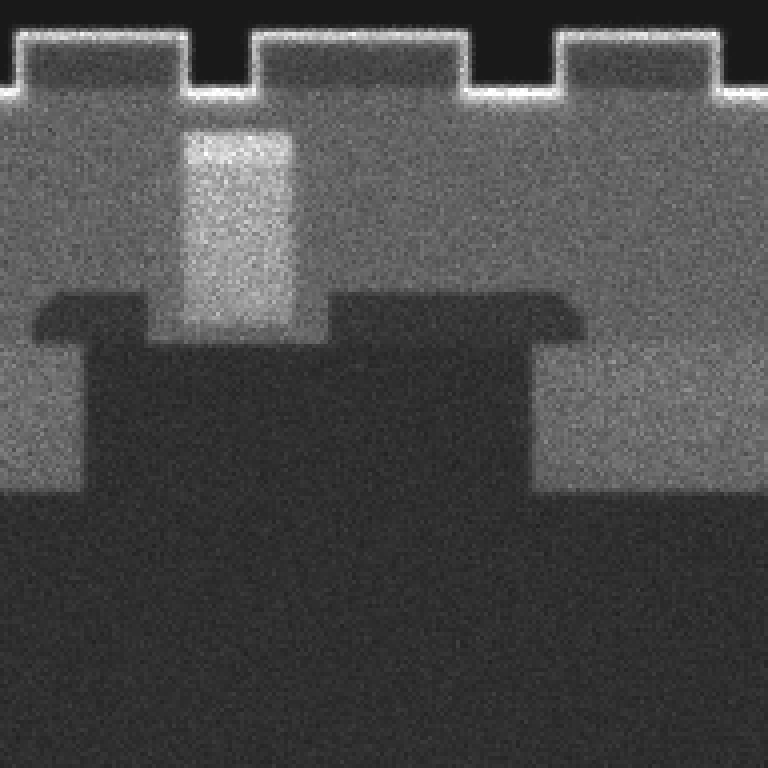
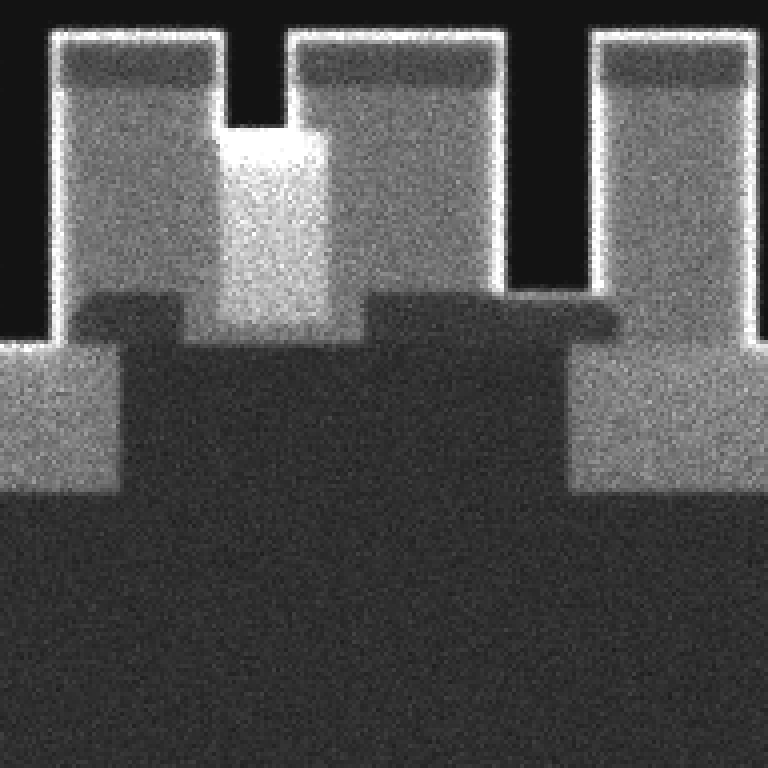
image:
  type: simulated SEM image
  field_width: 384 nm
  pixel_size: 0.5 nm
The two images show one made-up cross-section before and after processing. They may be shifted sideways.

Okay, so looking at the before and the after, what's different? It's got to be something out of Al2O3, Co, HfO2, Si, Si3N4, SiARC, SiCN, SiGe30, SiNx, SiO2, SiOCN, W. SiO2, removed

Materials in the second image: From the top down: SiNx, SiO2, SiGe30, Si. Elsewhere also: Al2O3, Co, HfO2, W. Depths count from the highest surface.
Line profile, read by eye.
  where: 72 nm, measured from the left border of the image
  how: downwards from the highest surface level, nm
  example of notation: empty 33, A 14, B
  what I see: SiNx 28, SiO2 102, SiGe30 26, Si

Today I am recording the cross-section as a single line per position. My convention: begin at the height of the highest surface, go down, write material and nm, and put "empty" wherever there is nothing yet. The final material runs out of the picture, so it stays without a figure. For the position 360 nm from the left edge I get SiNx 28, SiO2 128, Co 74, Si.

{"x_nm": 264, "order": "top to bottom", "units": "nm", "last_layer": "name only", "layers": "empty 130, SiGe30 26, Si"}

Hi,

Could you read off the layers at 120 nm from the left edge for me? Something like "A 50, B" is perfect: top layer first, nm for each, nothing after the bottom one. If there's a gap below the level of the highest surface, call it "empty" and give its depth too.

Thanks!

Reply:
empty 50, HfO2 16, W 80, Al2O3 10, Si